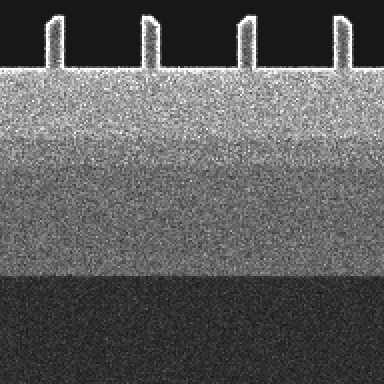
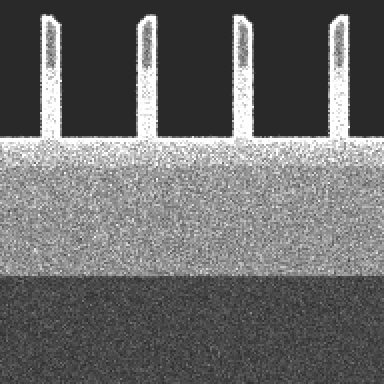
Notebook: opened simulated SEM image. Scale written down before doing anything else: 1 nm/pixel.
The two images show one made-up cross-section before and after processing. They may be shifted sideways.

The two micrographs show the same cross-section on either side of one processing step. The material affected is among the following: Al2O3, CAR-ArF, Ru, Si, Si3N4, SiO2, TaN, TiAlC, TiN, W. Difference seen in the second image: W removed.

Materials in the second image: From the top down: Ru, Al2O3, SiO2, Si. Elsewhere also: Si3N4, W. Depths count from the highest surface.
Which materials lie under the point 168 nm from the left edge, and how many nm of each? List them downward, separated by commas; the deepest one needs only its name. empty 122, Ru 28, Al2O3 44, SiO2 66, Si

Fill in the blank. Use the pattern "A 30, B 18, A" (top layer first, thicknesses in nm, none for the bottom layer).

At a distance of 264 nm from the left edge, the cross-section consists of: empty 122, Ru 28, Al2O3 44, SiO2 66, Si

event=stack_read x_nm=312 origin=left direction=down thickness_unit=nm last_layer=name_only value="empty 122, Ru 28, Al2O3 44, SiO2 66, Si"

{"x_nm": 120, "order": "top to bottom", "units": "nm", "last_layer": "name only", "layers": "empty 122, Ru 28, Al2O3 44, SiO2 66, Si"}